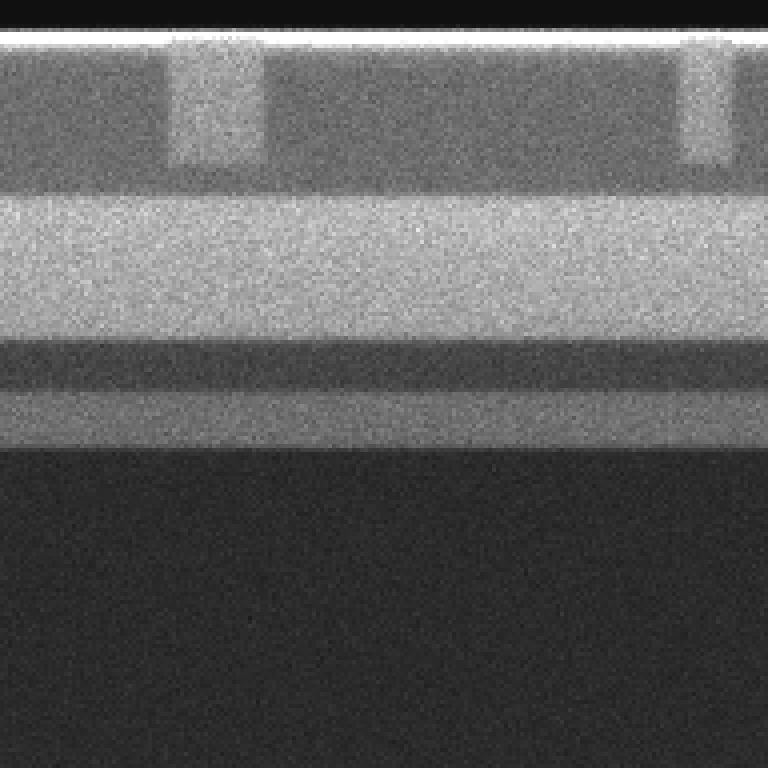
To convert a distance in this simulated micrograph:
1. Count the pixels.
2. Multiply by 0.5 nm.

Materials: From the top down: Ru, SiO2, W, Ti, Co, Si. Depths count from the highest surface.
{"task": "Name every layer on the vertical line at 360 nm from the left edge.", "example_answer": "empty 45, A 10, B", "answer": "Ru 66, SiO2 16, W 72, Ti 26, Co 28, Si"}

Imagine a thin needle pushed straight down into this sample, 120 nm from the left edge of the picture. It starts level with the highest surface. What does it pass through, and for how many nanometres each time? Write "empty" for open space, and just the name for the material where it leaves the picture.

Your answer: Ru 66, SiO2 16, W 72, Ti 26, Co 28, Si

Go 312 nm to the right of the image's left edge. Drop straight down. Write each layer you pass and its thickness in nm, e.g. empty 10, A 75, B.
SiO2 82, W 72, Ti 26, Co 28, Si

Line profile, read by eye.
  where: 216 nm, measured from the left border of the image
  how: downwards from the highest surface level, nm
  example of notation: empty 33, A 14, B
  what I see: SiO2 82, W 72, Ti 26, Co 28, Si